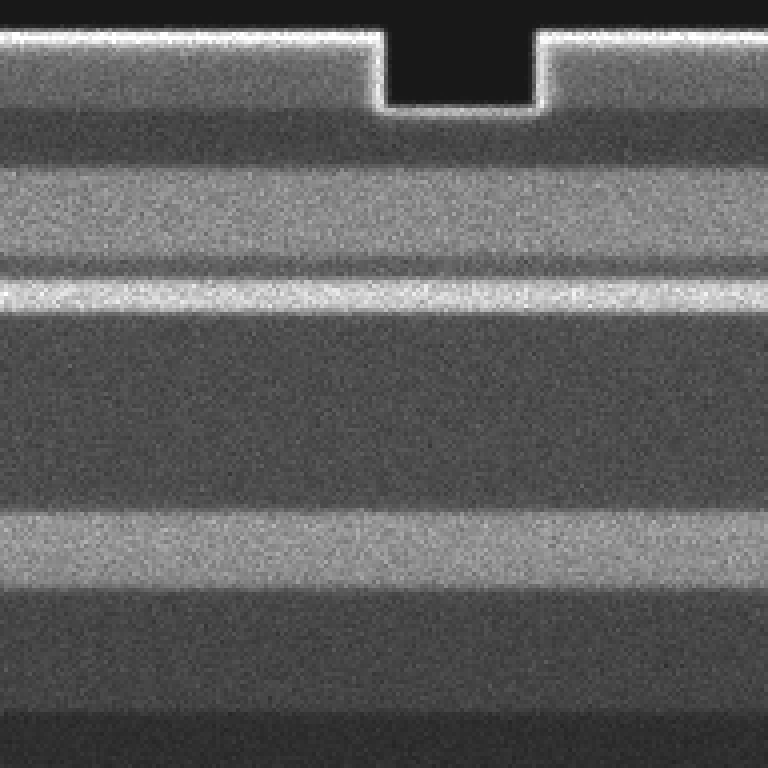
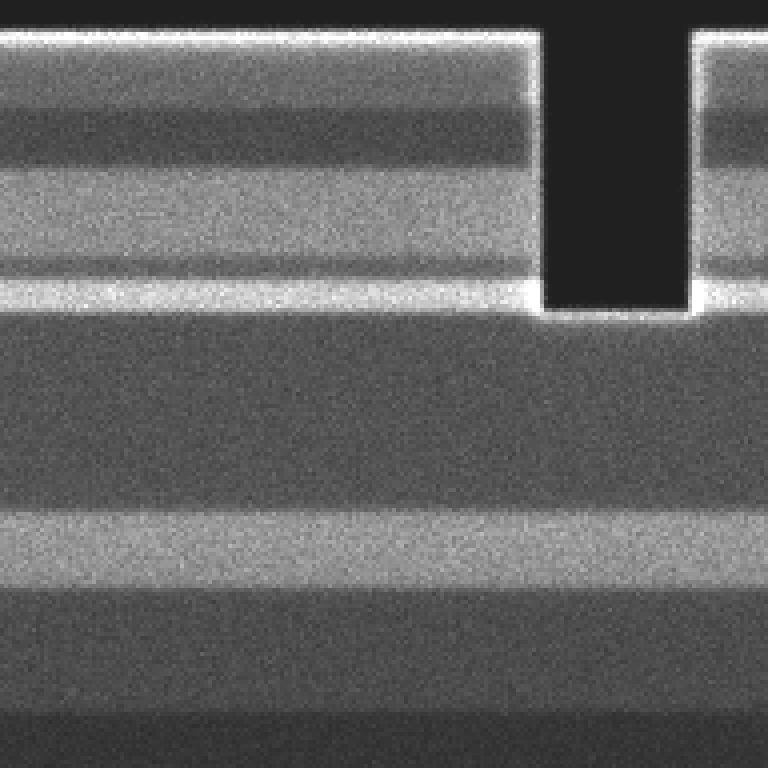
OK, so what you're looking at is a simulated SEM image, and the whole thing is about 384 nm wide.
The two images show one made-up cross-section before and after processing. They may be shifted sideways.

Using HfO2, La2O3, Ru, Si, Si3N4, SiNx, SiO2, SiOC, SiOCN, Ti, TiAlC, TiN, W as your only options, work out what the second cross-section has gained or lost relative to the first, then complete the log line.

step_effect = removed HfO2 and Ru and SiNx and TiN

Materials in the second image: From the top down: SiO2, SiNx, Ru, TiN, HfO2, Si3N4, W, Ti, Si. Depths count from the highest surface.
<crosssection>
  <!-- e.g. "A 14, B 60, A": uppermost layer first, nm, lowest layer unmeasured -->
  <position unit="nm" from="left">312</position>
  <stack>empty 140, Si3N4 100, W 38, Ti 62, Si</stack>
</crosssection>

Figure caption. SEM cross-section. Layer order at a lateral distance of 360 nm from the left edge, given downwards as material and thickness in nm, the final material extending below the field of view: SiO2 38, SiNx 30, Ru 44, TiN 12, HfO2 16, Si3N4 100, W 38, Ti 62, Si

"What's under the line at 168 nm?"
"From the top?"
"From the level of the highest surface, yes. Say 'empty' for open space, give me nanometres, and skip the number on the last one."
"SiO2 38, SiNx 30, Ru 44, TiN 12, HfO2 16, Si3N4 100, W 38, Ti 62, Si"